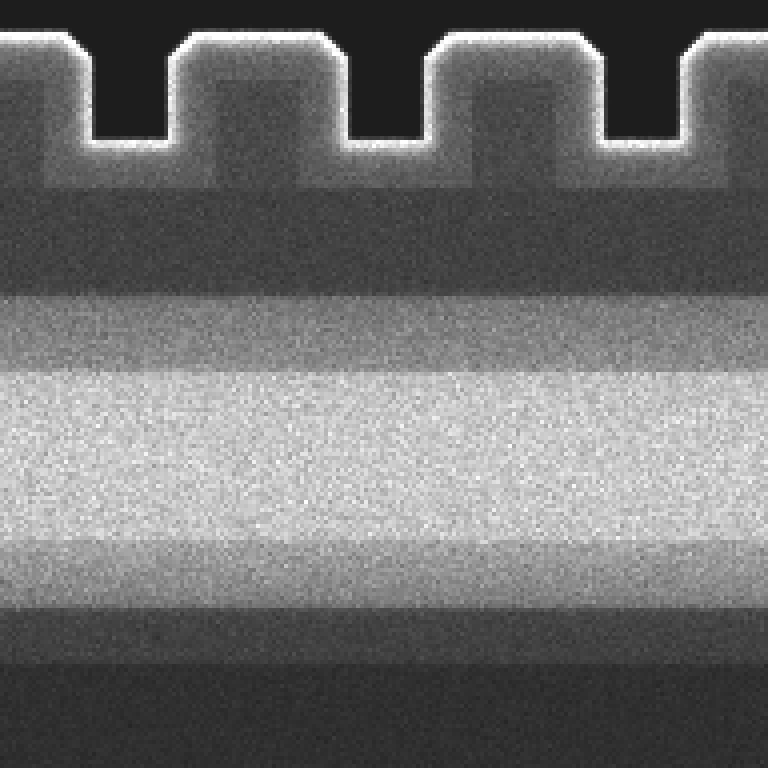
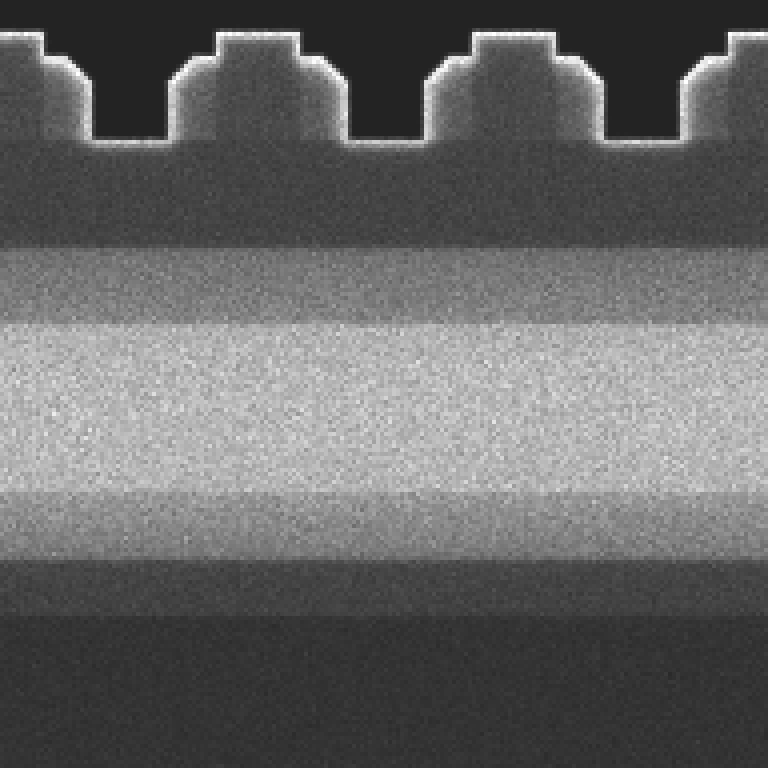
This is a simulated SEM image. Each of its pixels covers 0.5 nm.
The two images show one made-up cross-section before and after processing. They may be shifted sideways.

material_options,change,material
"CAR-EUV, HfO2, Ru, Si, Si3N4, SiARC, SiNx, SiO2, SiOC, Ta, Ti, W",removed,SiO2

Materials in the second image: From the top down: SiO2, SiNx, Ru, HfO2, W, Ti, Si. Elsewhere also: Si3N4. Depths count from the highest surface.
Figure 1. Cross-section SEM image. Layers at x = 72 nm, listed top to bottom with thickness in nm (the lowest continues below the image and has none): empty 54, SiNx 54, Ru 38, HfO2 84, W 34, Ti 28, Si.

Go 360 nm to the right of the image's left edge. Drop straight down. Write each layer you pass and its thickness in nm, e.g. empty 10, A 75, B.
empty 12, SiO2 42, SiNx 54, Ru 38, HfO2 84, W 34, Ti 28, Si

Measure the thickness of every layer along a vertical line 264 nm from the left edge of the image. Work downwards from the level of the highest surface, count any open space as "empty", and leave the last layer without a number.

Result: Si3N4 54, SiNx 54, Ru 38, HfO2 84, W 34, Ti 28, Si